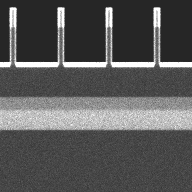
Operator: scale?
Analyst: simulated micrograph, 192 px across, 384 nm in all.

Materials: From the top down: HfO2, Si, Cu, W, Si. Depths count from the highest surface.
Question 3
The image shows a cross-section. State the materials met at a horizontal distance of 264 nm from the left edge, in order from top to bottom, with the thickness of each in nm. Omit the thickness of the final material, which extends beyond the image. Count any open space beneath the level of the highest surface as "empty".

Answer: empty 110, HfO2 8, Si 60, Cu 26, W 40, Si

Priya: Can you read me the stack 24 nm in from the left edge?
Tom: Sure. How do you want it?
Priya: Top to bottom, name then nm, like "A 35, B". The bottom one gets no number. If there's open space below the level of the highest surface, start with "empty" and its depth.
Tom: Si 178, Cu 26, W 40, Si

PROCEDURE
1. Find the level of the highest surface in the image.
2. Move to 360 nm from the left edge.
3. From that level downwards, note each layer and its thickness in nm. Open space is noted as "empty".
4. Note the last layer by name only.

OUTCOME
empty 110, HfO2 8, Si 60, Cu 26, W 40, Si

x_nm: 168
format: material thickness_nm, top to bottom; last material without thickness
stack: empty 110, HfO2 8, Si 60, Cu 26, W 40, Si